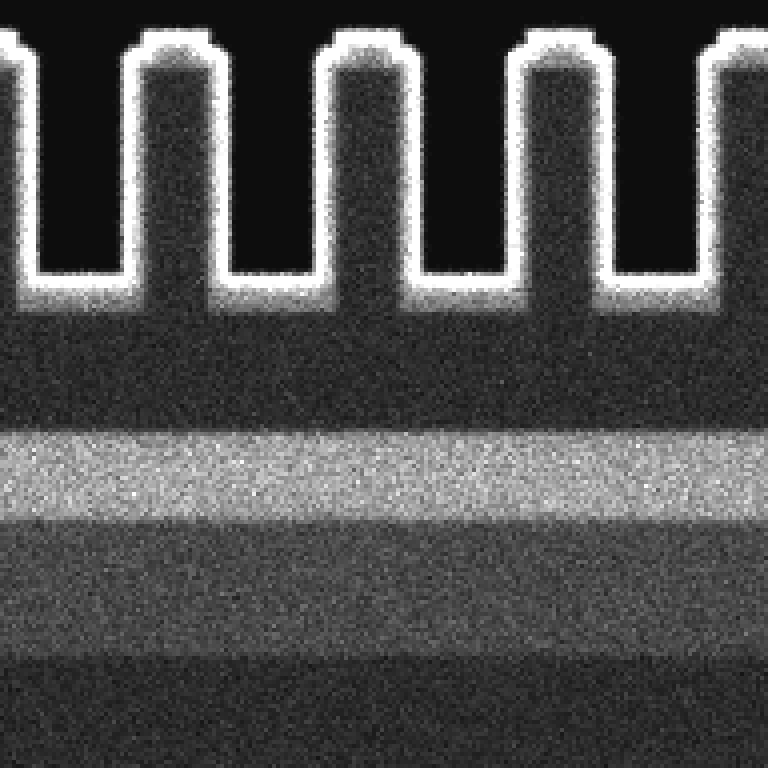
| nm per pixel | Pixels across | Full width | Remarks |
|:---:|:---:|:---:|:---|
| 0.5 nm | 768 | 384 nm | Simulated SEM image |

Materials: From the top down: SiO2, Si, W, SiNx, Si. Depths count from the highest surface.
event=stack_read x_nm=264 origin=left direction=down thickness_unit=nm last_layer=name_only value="SiO2 18, Si 182, W 44, SiNx 68, Si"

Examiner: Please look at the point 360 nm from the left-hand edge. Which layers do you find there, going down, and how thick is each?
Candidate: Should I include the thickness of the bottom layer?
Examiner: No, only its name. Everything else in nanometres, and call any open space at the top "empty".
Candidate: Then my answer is SiO2 18, Si 182, W 44, SiNx 68, Si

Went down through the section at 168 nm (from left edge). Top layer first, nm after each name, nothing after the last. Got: SiO2 18, Si 182, W 44, SiNx 68, Si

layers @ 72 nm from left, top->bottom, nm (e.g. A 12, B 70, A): SiO2 18, Si 182, W 44, SiNx 68, Si